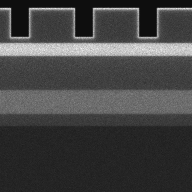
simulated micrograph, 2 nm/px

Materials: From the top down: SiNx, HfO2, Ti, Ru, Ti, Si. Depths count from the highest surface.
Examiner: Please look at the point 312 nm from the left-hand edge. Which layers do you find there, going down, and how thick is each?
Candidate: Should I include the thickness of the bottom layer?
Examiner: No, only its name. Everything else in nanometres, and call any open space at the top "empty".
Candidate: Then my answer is empty 58, SiNx 12, HfO2 26, Ti 68, Ru 48, Ti 24, Si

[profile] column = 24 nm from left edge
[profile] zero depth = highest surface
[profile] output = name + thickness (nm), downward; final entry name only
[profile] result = empty 58, SiNx 12, HfO2 26, Ti 68, Ru 48, Ti 24, Si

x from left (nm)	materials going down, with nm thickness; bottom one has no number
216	SiNx 70, HfO2 26, Ti 68, Ru 48, Ti 24, Si